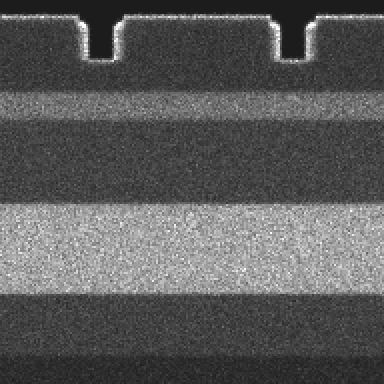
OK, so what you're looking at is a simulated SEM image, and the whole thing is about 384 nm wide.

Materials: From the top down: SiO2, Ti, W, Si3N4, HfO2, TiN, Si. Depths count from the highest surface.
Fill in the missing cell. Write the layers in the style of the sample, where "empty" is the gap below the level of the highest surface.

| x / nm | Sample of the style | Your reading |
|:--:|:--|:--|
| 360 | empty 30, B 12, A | Ti 76, W 28, Si3N4 84, HfO2 90, TiN 62, Si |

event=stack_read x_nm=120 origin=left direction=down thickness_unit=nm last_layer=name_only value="empty 6, SiO2 38, Ti 32, W 28, Si3N4 84, HfO2 90, TiN 62, Si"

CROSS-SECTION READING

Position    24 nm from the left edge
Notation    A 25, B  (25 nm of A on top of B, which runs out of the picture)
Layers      Ti 76, W 28, Si3N4 84, HfO2 90, TiN 62, Si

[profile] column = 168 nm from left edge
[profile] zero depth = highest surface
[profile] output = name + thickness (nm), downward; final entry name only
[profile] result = Ti 76, W 28, Si3N4 84, HfO2 90, TiN 62, Si